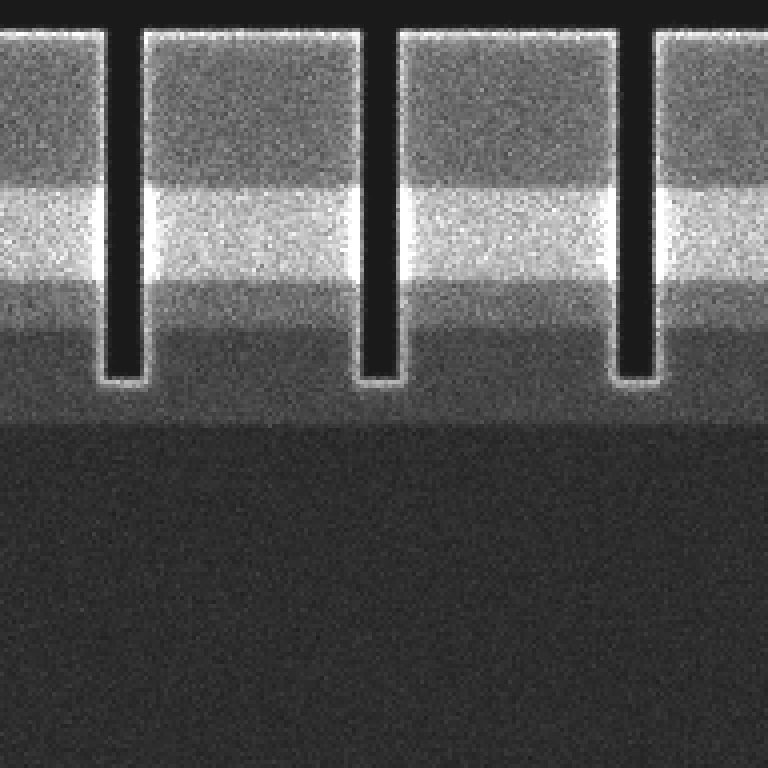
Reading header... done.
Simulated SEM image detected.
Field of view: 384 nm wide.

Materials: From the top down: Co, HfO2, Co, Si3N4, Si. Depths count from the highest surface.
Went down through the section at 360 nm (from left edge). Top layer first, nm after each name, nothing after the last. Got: Co 78, HfO2 46, Co 24, Si3N4 48, Si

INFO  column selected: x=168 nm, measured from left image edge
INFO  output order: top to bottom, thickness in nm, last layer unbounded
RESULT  Co 78, HfO2 46, Co 24, Si3N4 48, Si